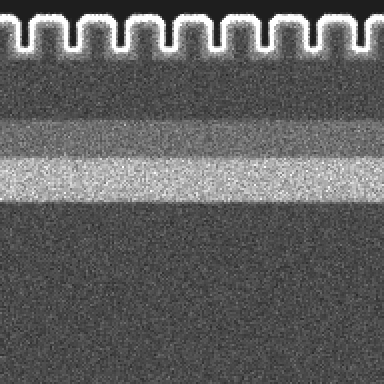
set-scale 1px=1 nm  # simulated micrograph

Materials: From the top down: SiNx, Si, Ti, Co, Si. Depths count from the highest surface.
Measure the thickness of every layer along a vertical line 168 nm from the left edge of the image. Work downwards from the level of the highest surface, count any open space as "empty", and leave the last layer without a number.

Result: empty 32, SiNx 12, Si 60, Ti 38, Co 44, Si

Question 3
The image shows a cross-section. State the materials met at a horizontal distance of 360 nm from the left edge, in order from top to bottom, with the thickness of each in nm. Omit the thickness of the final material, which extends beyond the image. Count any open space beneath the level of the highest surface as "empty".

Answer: empty 32, SiNx 12, Si 60, Ti 38, Co 44, Si